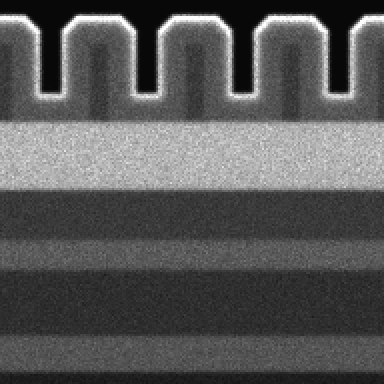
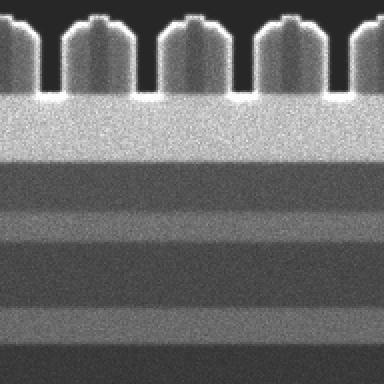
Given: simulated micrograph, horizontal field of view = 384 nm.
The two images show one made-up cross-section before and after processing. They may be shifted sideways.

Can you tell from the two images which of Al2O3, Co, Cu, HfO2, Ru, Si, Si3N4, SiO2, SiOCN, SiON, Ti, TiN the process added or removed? Yes, it removed SiO2.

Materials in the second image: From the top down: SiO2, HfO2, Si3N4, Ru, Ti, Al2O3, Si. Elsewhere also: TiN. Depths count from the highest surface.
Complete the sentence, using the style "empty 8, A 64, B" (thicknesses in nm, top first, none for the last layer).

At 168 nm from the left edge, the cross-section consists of empty 10, SiO2 68, HfO2 68, Si3N4 50, Ru 30, Ti 66, Al2O3 36, Si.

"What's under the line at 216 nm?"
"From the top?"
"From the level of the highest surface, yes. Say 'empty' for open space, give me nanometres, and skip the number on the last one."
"empty 6, SiO2 72, HfO2 68, Si3N4 50, Ru 30, Ti 66, Al2O3 36, Si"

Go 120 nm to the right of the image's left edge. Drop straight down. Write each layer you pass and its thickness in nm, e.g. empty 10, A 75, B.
empty 6, SiO2 72, HfO2 68, Si3N4 50, Ru 30, Ti 66, Al2O3 36, Si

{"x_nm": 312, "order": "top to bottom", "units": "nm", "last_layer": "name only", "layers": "empty 6, SiO2 72, HfO2 68, Si3N4 50, Ru 30, Ti 66, Al2O3 36, Si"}